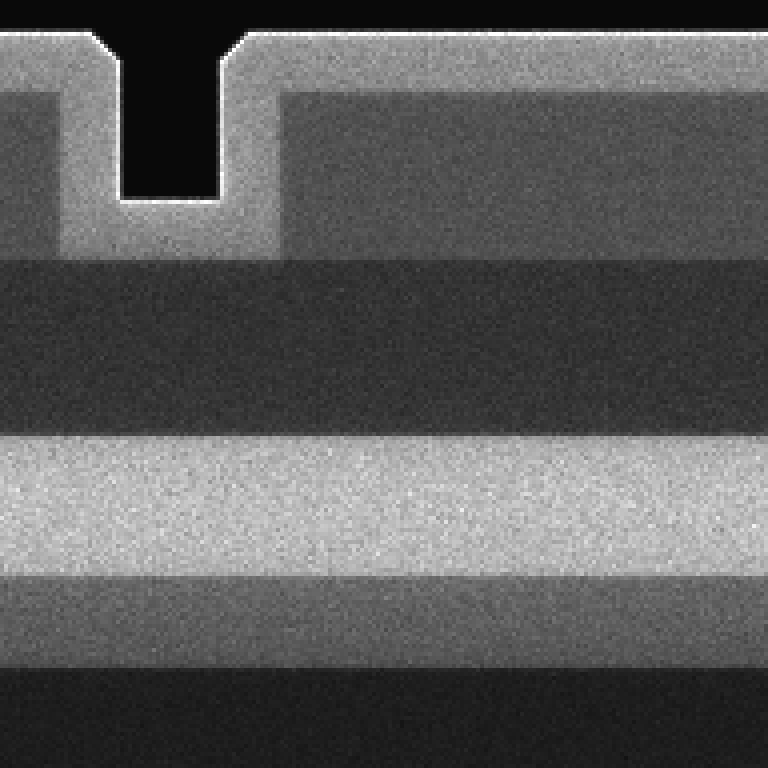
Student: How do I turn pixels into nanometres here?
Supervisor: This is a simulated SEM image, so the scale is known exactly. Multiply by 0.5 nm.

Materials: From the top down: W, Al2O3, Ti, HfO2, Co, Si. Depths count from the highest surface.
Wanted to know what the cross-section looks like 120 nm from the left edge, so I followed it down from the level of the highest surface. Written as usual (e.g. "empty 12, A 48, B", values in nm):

empty 4, W 110, Ti 88, HfO2 70, Co 46, Si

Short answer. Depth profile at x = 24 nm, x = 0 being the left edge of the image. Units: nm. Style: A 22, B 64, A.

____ W 30, Al2O3 84, Ti 88, HfO2 70, Co 46, Si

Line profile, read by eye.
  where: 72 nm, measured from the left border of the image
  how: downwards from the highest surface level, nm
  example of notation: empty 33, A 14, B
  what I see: empty 84, W 30, Ti 88, HfO2 70, Co 46, Si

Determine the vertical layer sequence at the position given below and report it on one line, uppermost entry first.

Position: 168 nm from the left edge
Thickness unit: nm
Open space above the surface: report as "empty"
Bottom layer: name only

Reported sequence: W 30, Al2O3 84, Ti 88, HfO2 70, Co 46, Si